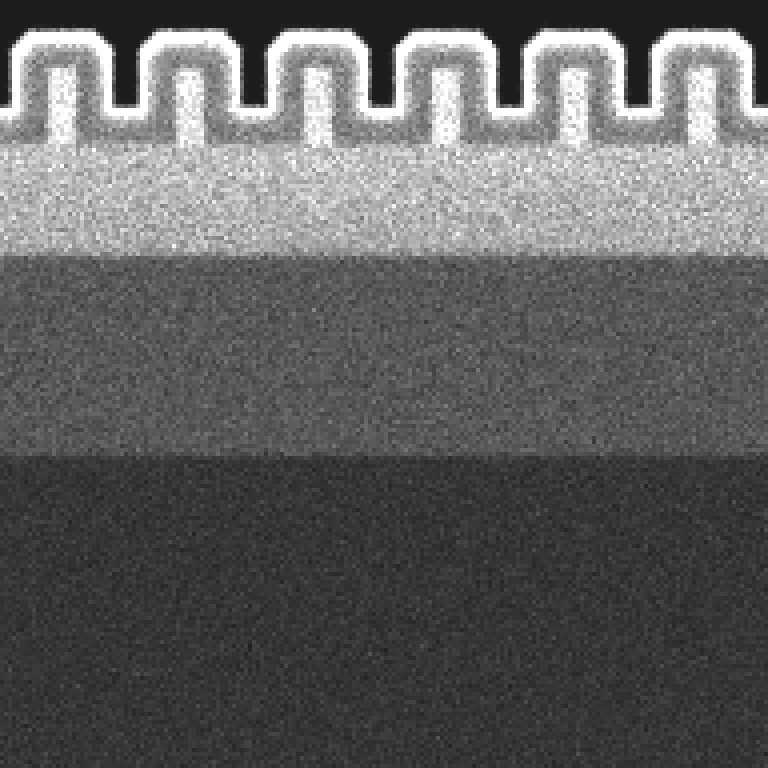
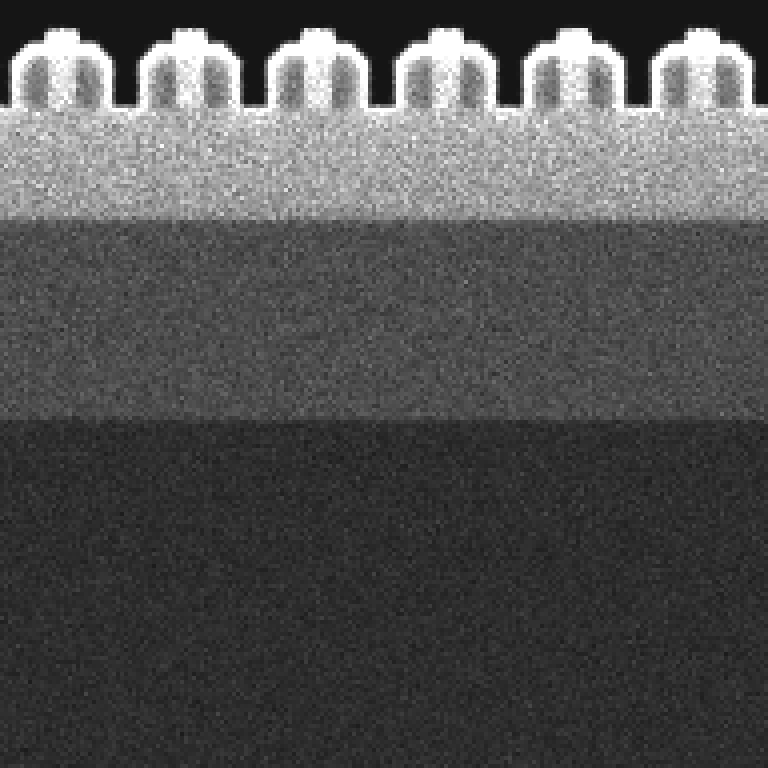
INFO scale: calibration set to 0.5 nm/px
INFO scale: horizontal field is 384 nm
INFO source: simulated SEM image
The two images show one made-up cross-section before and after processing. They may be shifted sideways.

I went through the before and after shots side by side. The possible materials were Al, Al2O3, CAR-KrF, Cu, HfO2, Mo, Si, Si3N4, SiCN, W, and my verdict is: removed, Al2O3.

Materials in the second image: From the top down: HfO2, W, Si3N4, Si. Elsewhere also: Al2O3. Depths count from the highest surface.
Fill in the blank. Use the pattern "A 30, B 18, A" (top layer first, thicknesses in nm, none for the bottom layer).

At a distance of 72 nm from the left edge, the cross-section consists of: empty 12, Al2O3 26, W 56, Si3N4 100, Si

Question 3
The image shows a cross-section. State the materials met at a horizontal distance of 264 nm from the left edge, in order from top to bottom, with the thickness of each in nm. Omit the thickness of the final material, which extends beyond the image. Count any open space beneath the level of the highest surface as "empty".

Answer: empty 12, Al2O3 26, W 56, Si3N4 100, Si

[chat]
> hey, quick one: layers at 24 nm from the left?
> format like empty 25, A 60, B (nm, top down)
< HfO2 38, W 56, Si3N4 100, Si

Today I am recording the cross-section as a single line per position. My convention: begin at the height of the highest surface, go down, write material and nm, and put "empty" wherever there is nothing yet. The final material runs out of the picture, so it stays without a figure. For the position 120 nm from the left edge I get empty 38, W 56, Si3N4 100, Si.